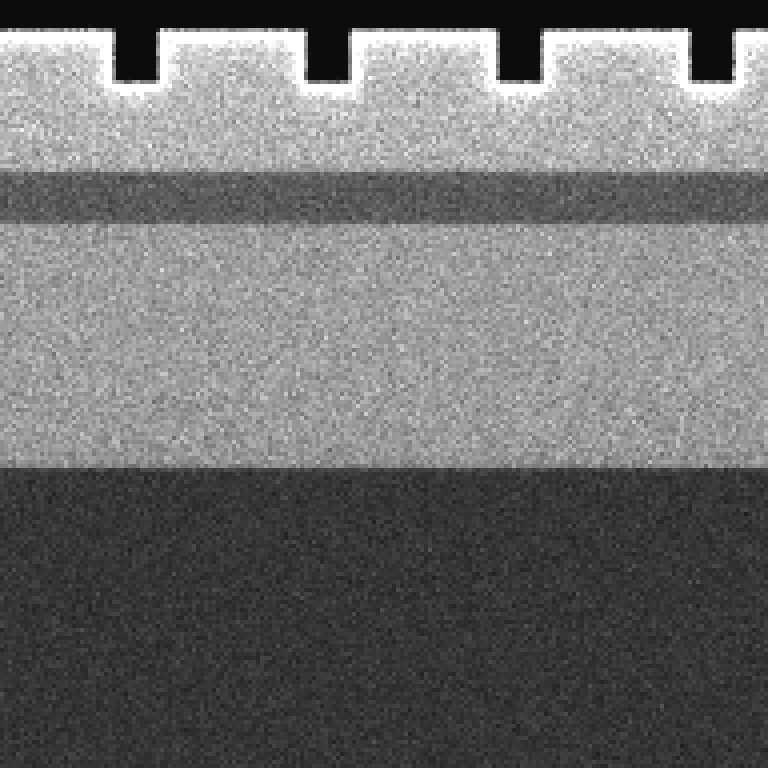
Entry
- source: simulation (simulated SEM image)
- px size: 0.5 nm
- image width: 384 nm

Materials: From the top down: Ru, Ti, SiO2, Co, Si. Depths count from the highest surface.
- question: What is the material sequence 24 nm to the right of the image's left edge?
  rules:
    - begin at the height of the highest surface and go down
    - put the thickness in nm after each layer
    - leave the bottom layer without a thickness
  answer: Ru 70, Ti 26, SiO2 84, Co 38, Si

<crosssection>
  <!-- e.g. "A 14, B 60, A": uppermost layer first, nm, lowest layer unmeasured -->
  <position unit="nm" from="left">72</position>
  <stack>empty 26, Ru 44, Ti 26, SiO2 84, Co 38, Si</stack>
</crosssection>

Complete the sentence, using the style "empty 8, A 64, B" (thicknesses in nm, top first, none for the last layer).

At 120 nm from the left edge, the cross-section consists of Ru 70, Ti 26, SiO2 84, Co 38, Si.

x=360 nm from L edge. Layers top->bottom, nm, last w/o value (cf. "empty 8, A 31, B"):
empty 26, Ru 44, Ti 26, SiO2 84, Co 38, Si